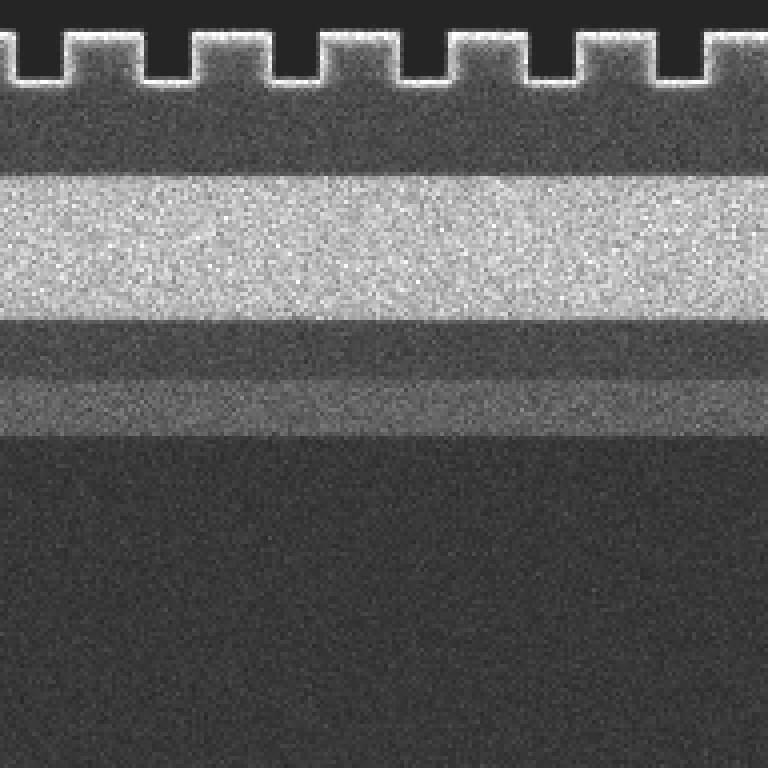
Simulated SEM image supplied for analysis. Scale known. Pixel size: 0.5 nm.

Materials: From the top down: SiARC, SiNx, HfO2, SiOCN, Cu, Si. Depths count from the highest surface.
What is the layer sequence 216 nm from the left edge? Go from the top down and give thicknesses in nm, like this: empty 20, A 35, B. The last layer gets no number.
empty 24, SiNx 48, HfO2 72, SiOCN 30, Cu 28, Si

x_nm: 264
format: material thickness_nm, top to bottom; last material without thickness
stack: empty 24, SiNx 48, HfO2 72, SiOCN 30, Cu 28, Si